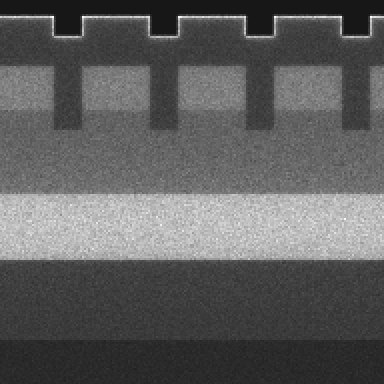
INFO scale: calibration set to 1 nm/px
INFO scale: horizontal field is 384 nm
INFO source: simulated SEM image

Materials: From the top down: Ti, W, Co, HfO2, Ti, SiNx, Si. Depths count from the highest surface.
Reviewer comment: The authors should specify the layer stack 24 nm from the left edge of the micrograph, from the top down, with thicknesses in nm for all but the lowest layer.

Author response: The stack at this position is Ti 50, W 44, Co 84, HfO2 66, Ti 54, SiNx 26, Si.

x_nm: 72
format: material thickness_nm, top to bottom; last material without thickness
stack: empty 20, Ti 94, Co 64, HfO2 66, Ti 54, SiNx 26, Si